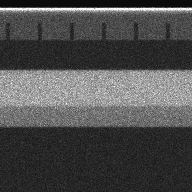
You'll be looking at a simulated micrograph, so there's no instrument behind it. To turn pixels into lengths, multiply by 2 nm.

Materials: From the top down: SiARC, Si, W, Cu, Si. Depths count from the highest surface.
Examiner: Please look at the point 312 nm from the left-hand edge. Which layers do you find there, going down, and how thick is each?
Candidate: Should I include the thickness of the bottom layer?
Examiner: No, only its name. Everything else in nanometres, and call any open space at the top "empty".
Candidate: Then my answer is SiARC 64, Si 60, W 72, Cu 42, Si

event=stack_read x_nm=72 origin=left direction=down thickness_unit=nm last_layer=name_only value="SiARC 64, Si 60, W 72, Cu 42, Si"